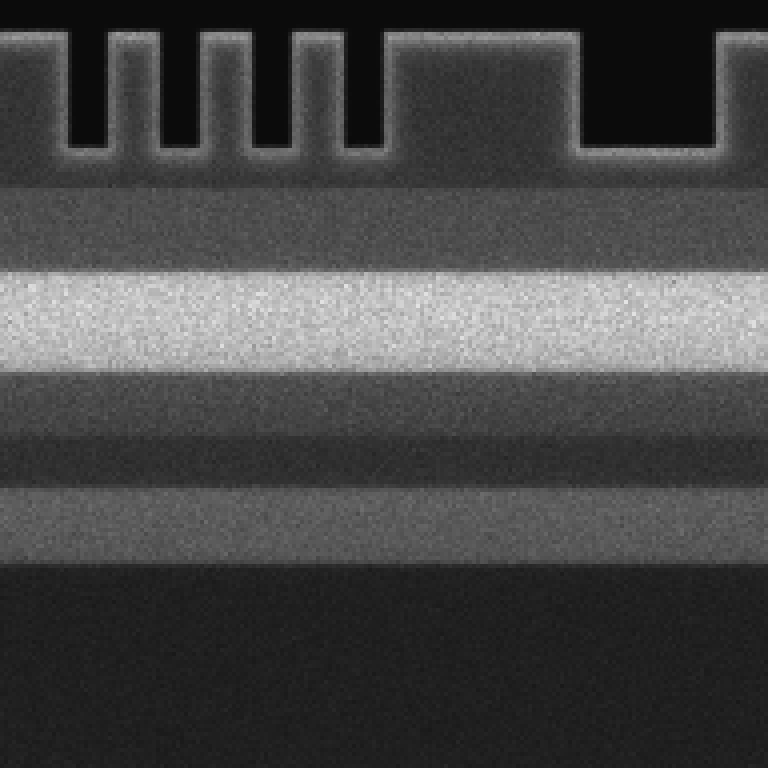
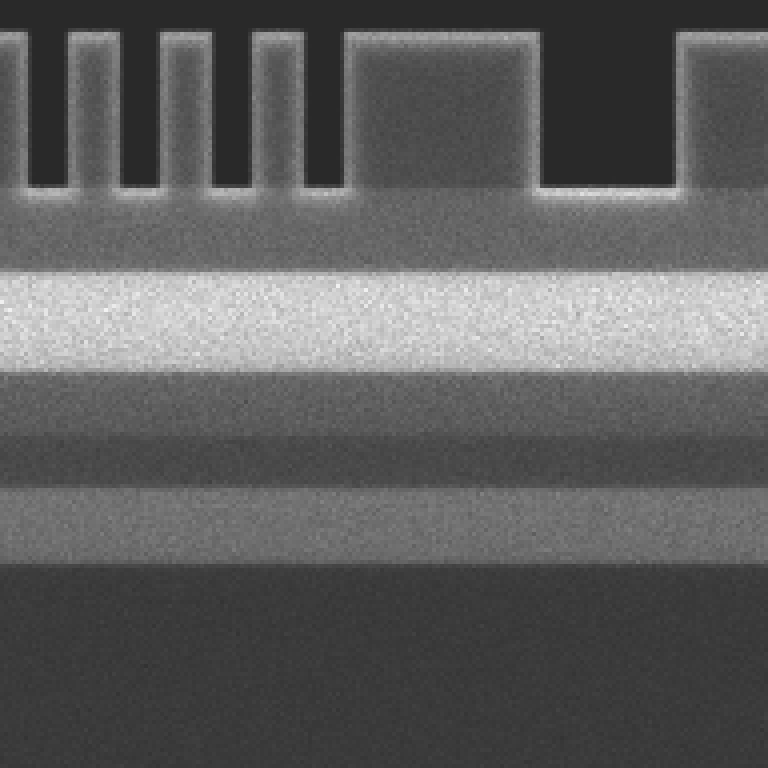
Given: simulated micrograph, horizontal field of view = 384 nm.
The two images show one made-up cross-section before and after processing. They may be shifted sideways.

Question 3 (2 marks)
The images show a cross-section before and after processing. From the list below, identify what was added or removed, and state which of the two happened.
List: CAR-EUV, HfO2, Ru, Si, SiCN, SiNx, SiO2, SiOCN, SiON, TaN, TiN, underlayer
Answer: underlayer was removed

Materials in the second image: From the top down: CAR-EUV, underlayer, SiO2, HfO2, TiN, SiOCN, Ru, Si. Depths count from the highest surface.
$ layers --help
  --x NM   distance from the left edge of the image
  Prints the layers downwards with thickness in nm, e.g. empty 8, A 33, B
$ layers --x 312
empty 78, SiO2 42, HfO2 50, TiN 32, SiOCN 26, Ru 38, Si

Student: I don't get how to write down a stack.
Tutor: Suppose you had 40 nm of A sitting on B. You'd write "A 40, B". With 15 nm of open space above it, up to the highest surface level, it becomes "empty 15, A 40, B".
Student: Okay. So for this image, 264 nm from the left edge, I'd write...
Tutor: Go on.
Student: CAR-EUV 58, underlayer 20, SiO2 42, HfO2 50, TiN 32, SiOCN 26, Ru 38, Si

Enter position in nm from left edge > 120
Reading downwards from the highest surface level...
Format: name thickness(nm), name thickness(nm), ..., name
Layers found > empty 78, SiO2 42, HfO2 50, TiN 32, SiOCN 26, Ru 38, Si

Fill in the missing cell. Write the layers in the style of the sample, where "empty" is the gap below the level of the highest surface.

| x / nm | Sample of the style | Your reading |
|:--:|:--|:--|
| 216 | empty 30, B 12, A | CAR-EUV 58, underlayer 20, SiO2 42, HfO2 50, TiN 32, SiOCN 26, Ru 38, Si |